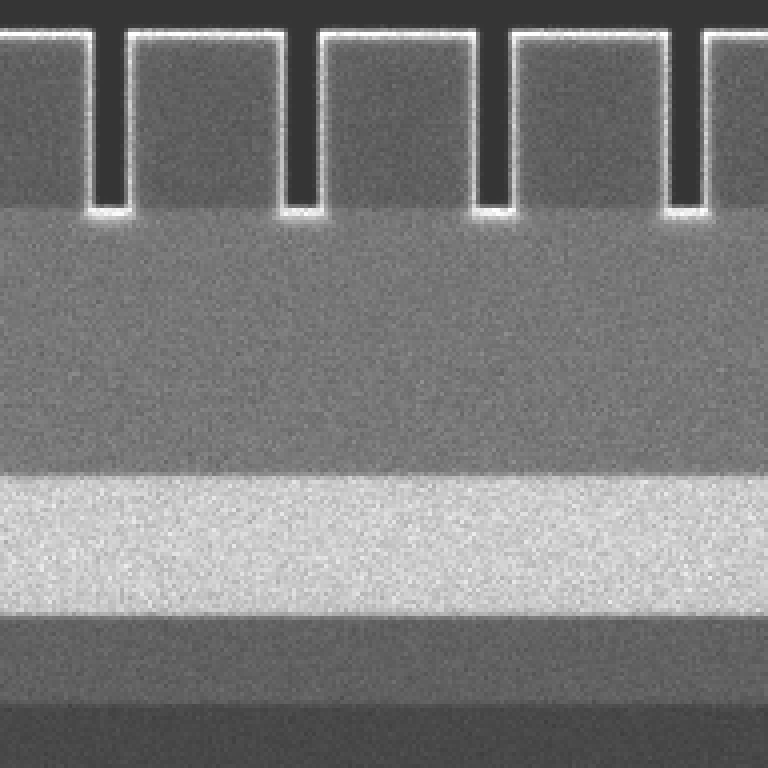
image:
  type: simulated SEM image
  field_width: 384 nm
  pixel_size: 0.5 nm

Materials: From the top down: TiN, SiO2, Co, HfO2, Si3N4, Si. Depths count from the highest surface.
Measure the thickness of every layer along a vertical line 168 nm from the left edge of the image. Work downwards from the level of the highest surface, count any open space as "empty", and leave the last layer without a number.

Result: TiN 88, SiO2 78, Co 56, HfO2 70, Si3N4 44, Si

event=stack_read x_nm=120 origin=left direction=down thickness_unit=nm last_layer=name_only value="TiN 88, SiO2 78, Co 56, HfO2 70, Si3N4 44, Si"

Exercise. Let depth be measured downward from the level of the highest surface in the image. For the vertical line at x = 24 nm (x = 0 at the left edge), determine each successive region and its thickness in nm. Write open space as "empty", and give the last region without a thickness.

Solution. TiN 88, SiO2 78, Co 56, HfO2 70, Si3N4 44, Si